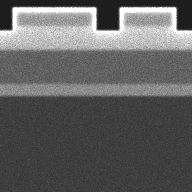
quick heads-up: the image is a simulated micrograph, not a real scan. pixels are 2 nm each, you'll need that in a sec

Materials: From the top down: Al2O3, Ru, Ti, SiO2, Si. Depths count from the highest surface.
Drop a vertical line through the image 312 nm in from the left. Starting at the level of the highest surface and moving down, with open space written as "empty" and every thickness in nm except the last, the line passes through Al2O3 36, Ru 48, Ti 68, SiO2 24, Si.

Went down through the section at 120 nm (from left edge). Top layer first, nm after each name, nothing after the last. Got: Al2O3 36, Ru 48, Ti 68, SiO2 24, Si